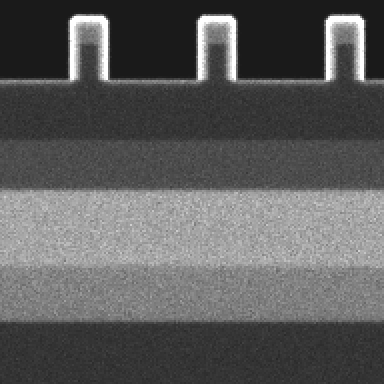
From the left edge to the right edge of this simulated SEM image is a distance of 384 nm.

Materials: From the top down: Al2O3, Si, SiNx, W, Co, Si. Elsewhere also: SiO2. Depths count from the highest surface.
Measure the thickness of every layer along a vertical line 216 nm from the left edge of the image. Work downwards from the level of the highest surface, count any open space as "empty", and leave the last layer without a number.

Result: SiO2 28, Si 96, SiNx 50, W 76, Co 56, Si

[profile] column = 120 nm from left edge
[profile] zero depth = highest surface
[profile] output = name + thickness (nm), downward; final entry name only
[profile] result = empty 64, Si 60, SiNx 50, W 76, Co 56, Si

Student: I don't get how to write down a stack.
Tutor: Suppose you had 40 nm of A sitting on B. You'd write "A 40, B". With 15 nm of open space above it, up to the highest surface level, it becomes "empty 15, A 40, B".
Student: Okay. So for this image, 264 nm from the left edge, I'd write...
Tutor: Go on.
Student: empty 64, Si 60, SiNx 50, W 76, Co 56, Si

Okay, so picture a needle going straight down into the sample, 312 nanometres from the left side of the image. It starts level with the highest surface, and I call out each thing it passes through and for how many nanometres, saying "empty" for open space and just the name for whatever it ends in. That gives empty 64, Si 60, SiNx 50, W 76, Co 56, Si